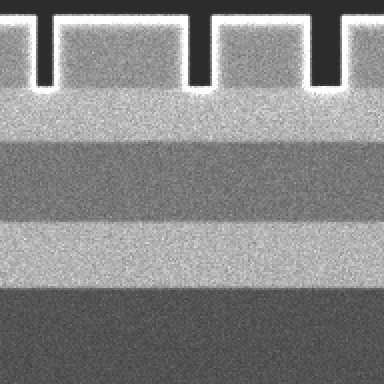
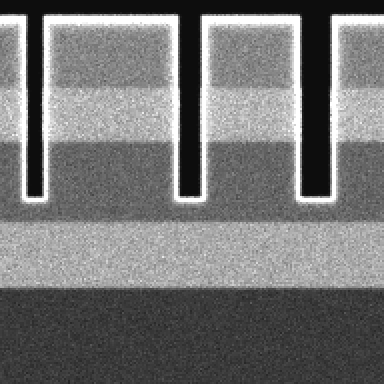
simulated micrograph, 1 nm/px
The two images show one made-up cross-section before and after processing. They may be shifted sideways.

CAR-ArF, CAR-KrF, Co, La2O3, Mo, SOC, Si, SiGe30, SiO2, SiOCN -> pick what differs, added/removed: Co and SiOCN removed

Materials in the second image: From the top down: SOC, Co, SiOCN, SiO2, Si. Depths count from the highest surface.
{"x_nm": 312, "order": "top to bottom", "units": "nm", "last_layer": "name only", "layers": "empty 182, SiOCN 24, SiO2 66, Si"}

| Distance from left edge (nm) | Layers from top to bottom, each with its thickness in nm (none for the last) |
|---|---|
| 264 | SOC 72, Co 54, SiOCN 80, SiO2 66, Si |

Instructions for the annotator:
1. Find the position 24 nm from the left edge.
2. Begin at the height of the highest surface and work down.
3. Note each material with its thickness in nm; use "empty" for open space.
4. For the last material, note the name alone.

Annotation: SOC 72, Co 54, SiOCN 80, SiO2 66, Si